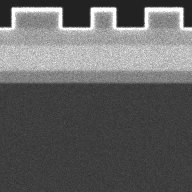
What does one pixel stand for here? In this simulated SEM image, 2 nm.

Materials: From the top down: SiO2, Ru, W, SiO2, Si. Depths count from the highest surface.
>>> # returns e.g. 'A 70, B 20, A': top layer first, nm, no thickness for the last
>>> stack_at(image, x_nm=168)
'empty 40, Ru 34, W 52, SiO2 24, Si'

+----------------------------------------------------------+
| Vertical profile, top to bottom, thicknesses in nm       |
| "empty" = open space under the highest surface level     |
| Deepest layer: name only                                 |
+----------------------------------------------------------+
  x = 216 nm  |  SiO2 40, Ru 34, W 52, SiO2 24, Si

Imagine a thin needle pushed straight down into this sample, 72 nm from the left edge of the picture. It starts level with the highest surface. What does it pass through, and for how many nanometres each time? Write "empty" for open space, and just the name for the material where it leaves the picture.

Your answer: SiO2 40, Ru 34, W 52, SiO2 24, Si